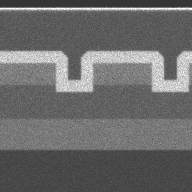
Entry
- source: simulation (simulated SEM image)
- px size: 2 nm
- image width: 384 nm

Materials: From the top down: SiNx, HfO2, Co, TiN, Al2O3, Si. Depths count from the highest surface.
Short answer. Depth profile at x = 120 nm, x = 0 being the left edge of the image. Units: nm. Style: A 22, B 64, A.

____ SiNx 86, HfO2 82, TiN 54, Al2O3 62, Si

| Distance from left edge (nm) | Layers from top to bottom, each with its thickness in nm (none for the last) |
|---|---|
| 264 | SiNx 86, HfO2 24, Co 44, TiN 68, Al2O3 62, Si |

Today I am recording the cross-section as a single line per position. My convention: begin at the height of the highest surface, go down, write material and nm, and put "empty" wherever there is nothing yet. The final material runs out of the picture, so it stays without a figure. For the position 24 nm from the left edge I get SiNx 86, HfO2 24, Co 44, TiN 68, Al2O3 62, Si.